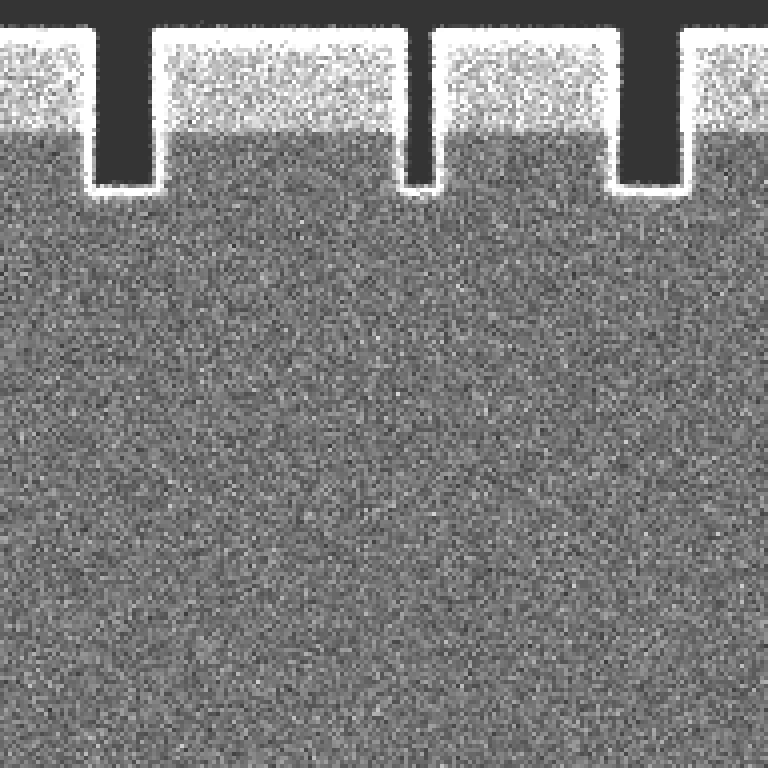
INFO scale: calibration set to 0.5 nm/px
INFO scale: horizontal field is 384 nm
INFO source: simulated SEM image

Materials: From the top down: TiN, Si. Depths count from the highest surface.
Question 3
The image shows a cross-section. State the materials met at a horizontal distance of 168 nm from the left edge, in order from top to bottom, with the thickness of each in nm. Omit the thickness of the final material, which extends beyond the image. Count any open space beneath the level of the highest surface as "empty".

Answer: TiN 50, Si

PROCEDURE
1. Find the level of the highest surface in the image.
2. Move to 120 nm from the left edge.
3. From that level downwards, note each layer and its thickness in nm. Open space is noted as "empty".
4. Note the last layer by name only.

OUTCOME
TiN 50, Si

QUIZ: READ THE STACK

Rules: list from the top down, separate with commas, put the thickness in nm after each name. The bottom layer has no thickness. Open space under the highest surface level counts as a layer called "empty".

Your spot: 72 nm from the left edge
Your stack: empty 78, Si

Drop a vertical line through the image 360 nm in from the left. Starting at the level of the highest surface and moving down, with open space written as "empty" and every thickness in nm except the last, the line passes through TiN 50, Si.